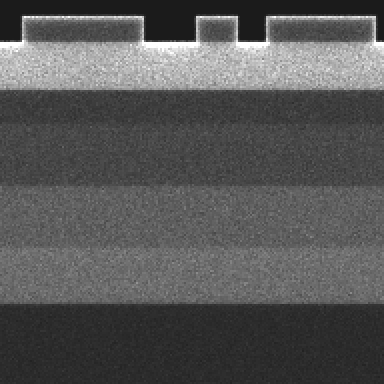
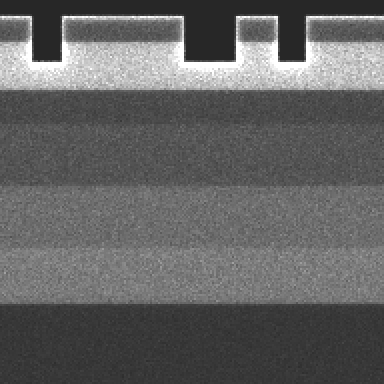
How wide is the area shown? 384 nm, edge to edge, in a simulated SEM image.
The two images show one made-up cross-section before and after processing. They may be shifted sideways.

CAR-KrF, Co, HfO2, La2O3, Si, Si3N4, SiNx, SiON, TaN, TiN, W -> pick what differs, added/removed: HfO2 removed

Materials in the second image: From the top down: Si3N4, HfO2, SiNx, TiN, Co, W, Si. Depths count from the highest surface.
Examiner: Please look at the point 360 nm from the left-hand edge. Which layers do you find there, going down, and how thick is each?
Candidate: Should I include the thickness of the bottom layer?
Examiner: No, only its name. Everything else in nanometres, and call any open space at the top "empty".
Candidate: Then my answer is Si3N4 26, HfO2 48, SiNx 34, TiN 62, Co 62, W 56, Si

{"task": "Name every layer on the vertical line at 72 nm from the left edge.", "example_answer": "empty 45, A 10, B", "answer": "Si3N4 26, HfO2 48, SiNx 34, TiN 62, Co 62, W 56, Si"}